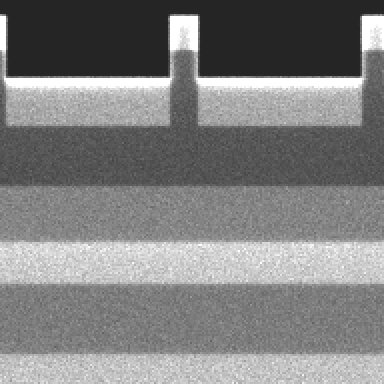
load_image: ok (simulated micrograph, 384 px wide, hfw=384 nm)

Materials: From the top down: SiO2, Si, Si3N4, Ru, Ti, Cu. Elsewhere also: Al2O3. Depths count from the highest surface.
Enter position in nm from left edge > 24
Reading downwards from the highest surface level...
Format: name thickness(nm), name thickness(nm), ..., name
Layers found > empty 62, SiO2 48, Si 60, Si3N4 56, Ru 42, Ti 70, Cu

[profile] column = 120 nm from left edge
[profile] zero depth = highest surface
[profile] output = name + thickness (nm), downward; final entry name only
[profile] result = empty 62, SiO2 48, Si 60, Si3N4 56, Ru 42, Ti 70, Cu